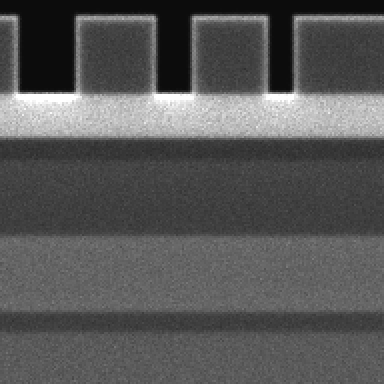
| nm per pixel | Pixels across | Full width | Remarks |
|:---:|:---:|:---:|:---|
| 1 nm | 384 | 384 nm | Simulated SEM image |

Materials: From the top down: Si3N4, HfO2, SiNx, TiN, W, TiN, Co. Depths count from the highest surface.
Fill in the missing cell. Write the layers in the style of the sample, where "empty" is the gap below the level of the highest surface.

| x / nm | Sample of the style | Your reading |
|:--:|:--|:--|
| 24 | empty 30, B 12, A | empty 78, HfO2 44, SiNx 22, TiN 76, W 76, TiN 20, Co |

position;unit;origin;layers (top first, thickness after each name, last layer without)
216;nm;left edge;Si3N4 78, HfO2 44, SiNx 22, TiN 76, W 76, TiN 20, Co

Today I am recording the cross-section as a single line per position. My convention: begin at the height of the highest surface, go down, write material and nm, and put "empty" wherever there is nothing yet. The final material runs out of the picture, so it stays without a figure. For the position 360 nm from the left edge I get Si3N4 78, HfO2 44, SiNx 22, TiN 76, W 76, TiN 20, Co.